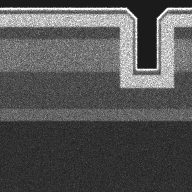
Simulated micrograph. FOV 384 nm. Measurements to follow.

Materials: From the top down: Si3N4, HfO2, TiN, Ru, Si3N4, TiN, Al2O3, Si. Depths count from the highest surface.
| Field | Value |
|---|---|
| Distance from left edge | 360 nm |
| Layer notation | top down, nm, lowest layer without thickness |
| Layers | Si3N4 12, HfO2 26, TiN 24, Ru 66, Si3N4 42, TiN 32, Al2O3 24, Si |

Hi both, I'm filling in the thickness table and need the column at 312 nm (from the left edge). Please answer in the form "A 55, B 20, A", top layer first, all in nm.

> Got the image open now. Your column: empty 122, Si3N4 12, HfO2 26, Si3N4 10, TiN 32, Al2O3 24, Si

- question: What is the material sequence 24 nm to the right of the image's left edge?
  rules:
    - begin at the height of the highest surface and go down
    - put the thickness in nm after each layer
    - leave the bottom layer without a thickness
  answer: Si3N4 12, HfO2 26, TiN 24, Ru 66, Si3N4 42, TiN 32, Al2O3 24, Si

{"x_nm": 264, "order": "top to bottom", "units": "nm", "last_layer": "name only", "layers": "empty 12, Si3N4 12, HfO2 136, Si3N4 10, TiN 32, Al2O3 24, Si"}